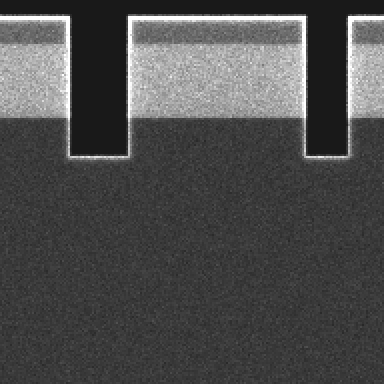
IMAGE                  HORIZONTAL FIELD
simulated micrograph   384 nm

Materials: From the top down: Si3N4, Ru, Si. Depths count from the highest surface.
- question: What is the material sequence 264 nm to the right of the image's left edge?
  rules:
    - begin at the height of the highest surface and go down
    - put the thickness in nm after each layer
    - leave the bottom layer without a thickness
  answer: Si3N4 28, Ru 74, Si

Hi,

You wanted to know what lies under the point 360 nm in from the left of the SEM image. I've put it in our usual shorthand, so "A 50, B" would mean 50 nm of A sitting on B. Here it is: Si3N4 28, Ru 74, Si